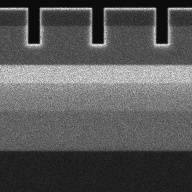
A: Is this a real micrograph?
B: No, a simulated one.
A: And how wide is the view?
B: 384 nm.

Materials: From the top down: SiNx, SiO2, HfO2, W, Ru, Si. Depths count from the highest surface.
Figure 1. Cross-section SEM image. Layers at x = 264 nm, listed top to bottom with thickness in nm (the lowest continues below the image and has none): SiNx 36, SiO2 78, HfO2 36, W 56, Ru 80, Si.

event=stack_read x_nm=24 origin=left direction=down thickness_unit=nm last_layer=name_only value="SiNx 36, SiO2 78, HfO2 36, W 56, Ru 80, Si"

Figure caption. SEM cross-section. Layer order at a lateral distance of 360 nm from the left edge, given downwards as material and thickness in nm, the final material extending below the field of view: SiNx 36, SiO2 78, HfO2 36, W 56, Ru 80, Si